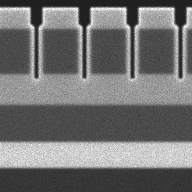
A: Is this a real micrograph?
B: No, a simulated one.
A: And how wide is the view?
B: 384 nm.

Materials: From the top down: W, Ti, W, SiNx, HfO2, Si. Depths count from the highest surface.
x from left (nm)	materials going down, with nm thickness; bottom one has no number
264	empty 142, W 52, SiNx 74, HfO2 52, Si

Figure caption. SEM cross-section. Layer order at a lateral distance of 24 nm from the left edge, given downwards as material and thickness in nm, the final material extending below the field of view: W 42, Ti 90, W 62, SiNx 74, HfO2 52, Si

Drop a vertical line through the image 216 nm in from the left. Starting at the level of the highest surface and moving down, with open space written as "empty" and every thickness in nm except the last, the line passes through W 42, Ti 90, W 62, SiNx 74, HfO2 52, Si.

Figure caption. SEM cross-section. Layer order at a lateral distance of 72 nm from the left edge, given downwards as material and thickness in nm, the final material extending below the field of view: empty 142, W 52, SiNx 74, HfO2 52, Si